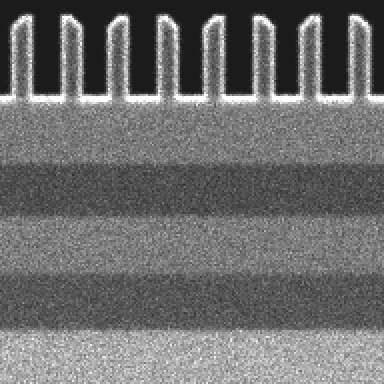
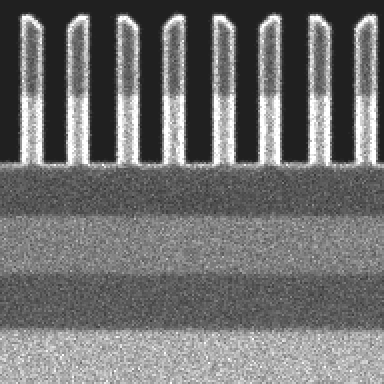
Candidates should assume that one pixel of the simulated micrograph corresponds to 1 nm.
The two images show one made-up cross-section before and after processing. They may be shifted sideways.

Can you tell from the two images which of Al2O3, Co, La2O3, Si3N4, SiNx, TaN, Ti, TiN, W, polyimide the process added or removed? Yes, it removed Al2O3.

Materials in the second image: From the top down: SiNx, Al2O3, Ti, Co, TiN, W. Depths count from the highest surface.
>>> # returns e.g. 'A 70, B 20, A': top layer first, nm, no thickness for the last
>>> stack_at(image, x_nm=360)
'empty 6, SiNx 74, Al2O3 68, Ti 52, Co 58, TiN 56, W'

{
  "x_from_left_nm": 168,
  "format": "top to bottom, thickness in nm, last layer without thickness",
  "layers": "empty 6, SiNx 74, Al2O3 68, Ti 52, Co 58, TiN 56, W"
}